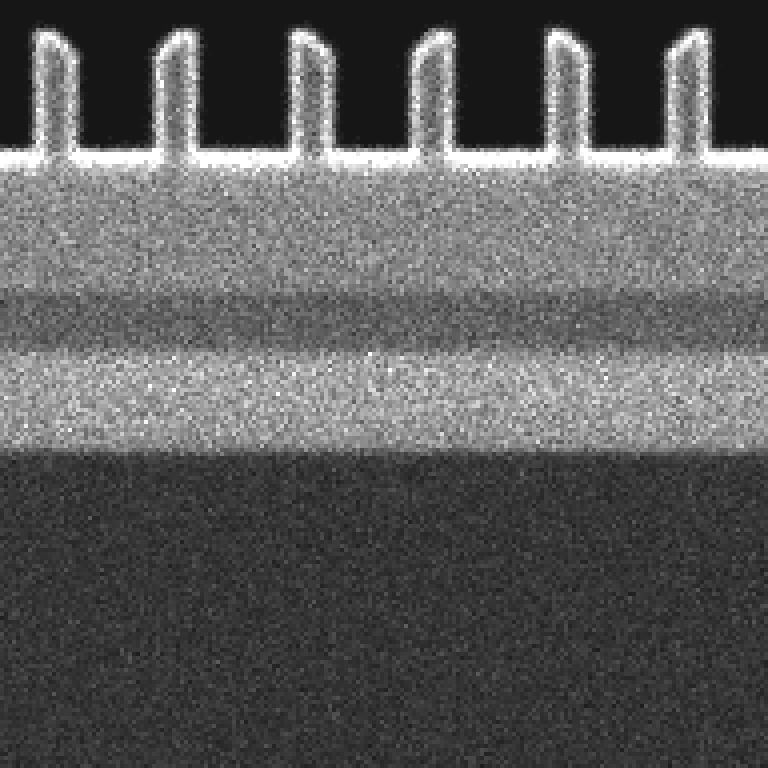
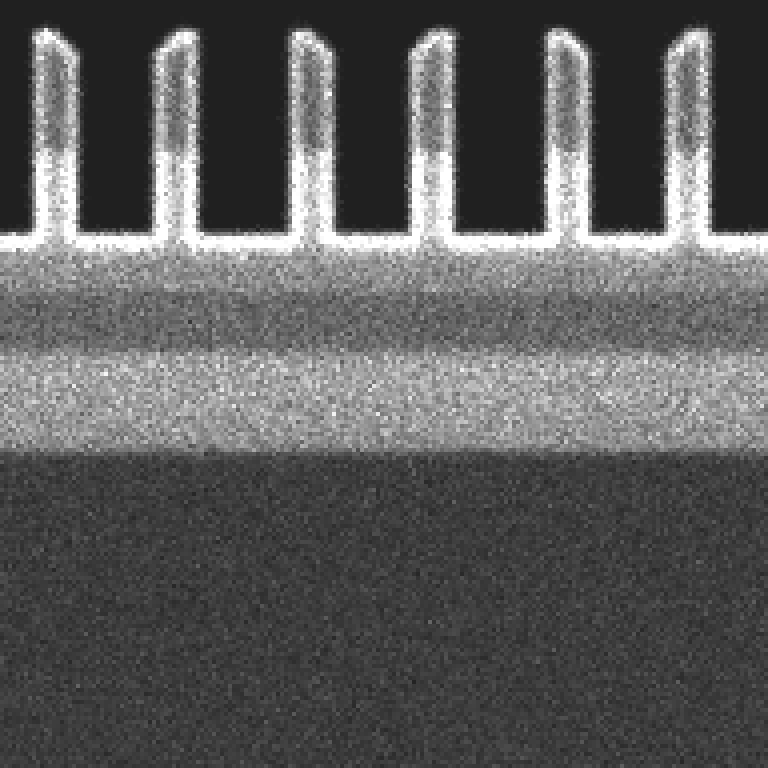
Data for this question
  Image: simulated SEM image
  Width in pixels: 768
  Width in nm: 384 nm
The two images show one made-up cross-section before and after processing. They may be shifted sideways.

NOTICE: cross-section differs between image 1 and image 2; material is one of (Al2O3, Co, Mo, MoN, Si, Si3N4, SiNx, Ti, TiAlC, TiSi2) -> removed: Al2O3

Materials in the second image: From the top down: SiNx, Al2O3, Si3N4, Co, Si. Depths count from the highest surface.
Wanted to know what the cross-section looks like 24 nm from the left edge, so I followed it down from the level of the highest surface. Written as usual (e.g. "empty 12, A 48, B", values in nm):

SiNx 60, Al2O3 70, Si3N4 30, Co 50, Si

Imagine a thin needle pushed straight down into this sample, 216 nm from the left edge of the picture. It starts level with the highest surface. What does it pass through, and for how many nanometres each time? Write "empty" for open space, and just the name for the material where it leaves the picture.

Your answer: SiNx 60, Al2O3 70, Si3N4 30, Co 50, Si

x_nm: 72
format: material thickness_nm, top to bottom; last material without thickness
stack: empty 102, Al2O3 28, Si3N4 30, Co 50, Si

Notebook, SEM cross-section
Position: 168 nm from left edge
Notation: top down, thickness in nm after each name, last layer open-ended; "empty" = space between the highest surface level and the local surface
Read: empty 102, Al2O3 28, Si3N4 30, Co 50, Si